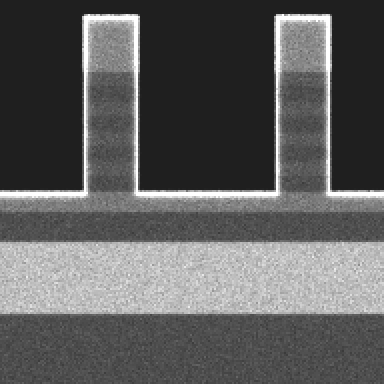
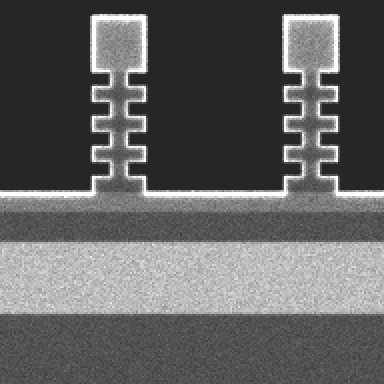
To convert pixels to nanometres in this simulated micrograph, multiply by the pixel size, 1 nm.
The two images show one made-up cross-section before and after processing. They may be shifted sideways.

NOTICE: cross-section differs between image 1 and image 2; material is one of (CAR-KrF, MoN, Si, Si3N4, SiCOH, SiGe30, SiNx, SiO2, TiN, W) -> removed: SiGe30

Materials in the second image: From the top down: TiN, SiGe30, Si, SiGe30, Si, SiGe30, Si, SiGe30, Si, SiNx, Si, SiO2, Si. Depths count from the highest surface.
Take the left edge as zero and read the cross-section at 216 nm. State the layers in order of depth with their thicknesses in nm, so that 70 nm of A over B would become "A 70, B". empty 176, SiNx 20, Si 30, SiO2 72, Si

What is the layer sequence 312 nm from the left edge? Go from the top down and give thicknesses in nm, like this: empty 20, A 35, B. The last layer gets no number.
TiN 56, SiGe30 14, Si 16, SiGe30 14, Si 16, SiGe30 14, Si 16, SiGe30 14, Si 16, SiNx 20, Si 30, SiO2 72, Si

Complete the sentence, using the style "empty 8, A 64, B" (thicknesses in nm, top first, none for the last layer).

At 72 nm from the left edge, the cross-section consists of empty 176, SiNx 20, Si 30, SiO2 72, Si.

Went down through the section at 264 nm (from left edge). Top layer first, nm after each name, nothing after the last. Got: empty 176, SiNx 20, Si 30, SiO2 72, Si